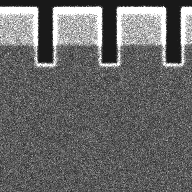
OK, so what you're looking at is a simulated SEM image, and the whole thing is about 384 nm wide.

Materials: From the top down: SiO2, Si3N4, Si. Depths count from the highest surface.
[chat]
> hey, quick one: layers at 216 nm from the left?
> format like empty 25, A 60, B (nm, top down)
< empty 112, Si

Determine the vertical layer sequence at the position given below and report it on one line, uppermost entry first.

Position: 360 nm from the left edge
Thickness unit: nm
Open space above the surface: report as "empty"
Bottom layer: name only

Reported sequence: empty 112, Si